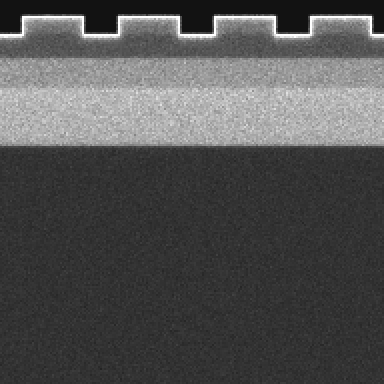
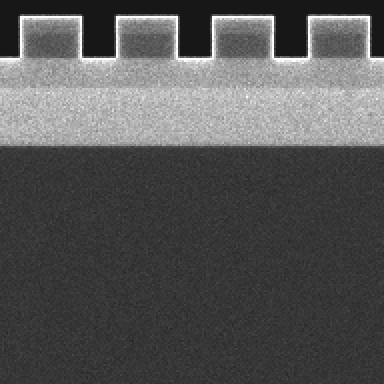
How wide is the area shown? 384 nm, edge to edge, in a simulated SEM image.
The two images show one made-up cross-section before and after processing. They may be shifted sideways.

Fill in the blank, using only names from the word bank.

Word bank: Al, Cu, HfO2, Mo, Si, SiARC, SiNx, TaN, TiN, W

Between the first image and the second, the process removed SiNx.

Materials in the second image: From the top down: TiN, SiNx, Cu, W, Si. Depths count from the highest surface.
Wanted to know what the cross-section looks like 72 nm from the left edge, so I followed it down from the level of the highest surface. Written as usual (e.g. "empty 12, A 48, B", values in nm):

TiN 18, SiNx 24, Cu 30, W 58, Si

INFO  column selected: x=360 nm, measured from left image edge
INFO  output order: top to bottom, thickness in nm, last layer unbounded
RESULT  TiN 18, SiNx 24, Cu 30, W 58, Si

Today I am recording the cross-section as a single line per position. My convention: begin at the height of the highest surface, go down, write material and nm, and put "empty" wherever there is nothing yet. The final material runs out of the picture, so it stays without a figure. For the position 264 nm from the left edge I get TiN 18, SiNx 24, Cu 30, W 58, Si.